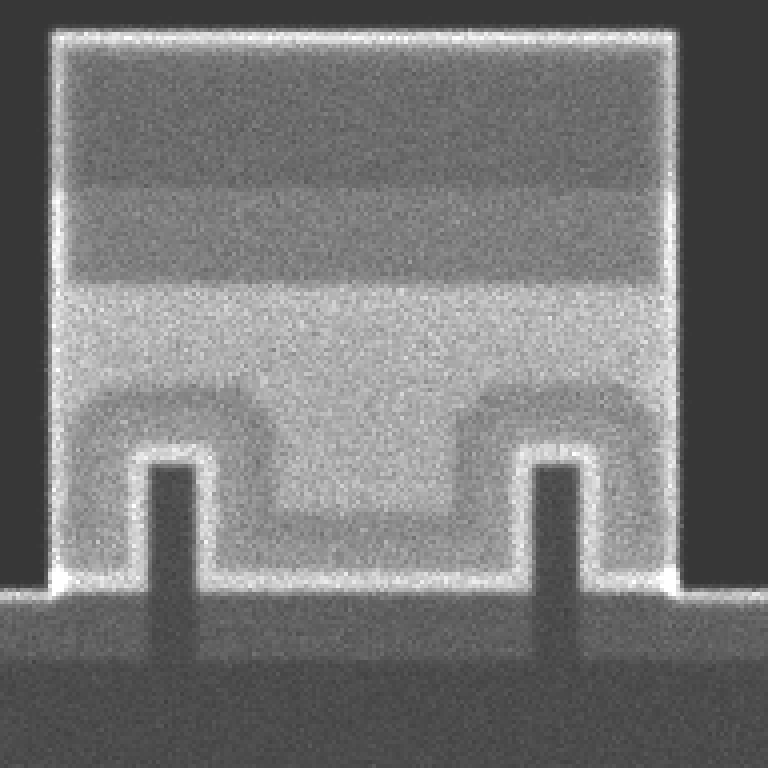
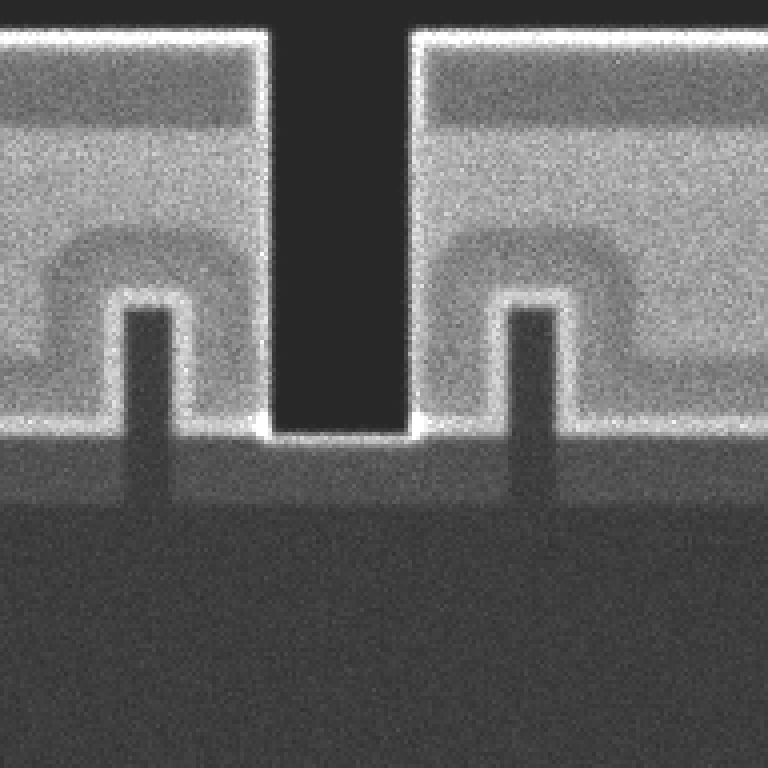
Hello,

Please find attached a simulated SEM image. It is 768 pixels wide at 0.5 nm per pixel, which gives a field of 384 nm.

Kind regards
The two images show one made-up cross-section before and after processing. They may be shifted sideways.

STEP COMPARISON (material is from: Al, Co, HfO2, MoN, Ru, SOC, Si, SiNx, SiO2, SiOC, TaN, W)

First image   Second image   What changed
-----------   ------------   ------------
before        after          SOC, removed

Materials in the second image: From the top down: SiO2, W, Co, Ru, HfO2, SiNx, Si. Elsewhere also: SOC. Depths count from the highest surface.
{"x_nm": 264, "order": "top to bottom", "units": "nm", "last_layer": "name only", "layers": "SiO2 48, W 50, Co 14, Ru 16, HfO2 10, Si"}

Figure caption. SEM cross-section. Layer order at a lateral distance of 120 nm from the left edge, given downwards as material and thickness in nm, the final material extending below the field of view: SiO2 48, W 64, Co 64, Ru 16, HfO2 10, SiNx 34, Si